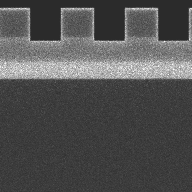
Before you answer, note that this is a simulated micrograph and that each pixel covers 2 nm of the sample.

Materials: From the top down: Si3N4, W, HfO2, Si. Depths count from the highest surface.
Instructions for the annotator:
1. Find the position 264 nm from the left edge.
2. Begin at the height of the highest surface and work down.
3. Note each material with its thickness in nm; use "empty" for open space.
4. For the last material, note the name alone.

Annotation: Si3N4 58, W 50, HfO2 34, Si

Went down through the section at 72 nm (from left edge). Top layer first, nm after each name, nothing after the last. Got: empty 66, W 42, HfO2 34, Si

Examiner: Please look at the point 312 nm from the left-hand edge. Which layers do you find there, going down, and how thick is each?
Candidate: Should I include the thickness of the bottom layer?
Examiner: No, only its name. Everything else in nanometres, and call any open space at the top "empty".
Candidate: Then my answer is Si3N4 58, W 50, HfO2 34, Si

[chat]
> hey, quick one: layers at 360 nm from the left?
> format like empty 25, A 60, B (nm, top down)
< empty 66, W 42, HfO2 34, Si